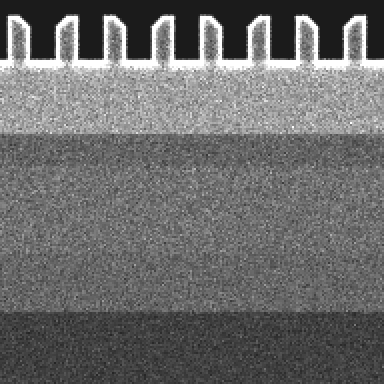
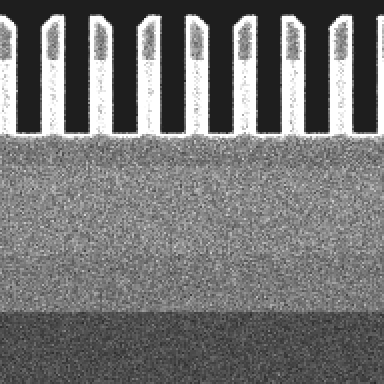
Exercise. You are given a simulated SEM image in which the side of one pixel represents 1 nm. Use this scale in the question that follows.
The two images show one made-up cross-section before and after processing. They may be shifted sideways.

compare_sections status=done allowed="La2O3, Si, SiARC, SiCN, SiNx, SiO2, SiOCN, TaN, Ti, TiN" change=removed material="SiO2"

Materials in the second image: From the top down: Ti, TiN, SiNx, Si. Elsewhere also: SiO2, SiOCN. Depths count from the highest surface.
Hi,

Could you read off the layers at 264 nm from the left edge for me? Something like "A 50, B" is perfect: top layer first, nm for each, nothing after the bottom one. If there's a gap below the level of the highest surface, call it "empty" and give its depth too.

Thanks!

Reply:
empty 118, Ti 32, TiN 88, SiNx 58, Si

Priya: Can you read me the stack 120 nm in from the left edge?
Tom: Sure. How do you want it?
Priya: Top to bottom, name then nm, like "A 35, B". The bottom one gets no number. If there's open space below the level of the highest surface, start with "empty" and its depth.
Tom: empty 118, Ti 32, TiN 88, SiNx 58, Si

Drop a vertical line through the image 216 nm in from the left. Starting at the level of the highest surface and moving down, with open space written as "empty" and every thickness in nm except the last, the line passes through empty 118, Ti 32, TiN 88, SiNx 58, Si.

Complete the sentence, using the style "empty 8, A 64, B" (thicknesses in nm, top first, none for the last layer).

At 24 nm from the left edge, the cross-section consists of empty 118, Ti 32, TiN 88, SiNx 58, Si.